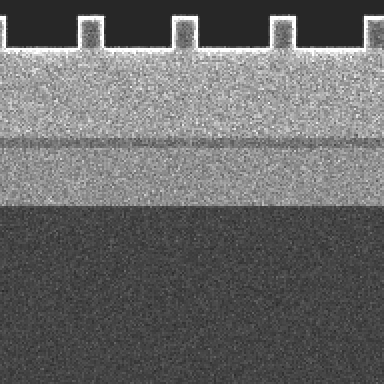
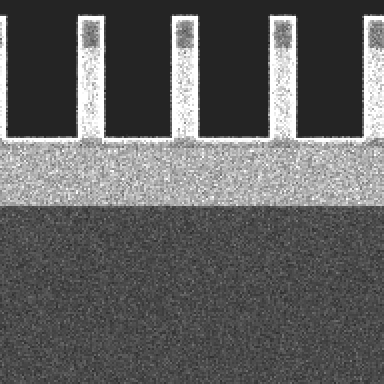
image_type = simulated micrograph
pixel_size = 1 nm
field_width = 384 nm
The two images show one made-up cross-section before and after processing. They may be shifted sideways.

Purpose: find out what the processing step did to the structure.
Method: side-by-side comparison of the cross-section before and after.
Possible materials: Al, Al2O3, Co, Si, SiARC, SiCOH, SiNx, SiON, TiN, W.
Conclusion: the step removed Co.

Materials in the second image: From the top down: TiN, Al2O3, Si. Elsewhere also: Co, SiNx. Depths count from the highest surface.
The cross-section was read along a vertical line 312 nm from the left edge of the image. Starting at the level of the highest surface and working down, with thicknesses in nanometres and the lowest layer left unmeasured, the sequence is empty 122, TiN 10, Al2O3 58, Si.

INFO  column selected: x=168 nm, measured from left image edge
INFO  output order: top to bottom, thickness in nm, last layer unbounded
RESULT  empty 122, TiN 10, Al2O3 58, Si